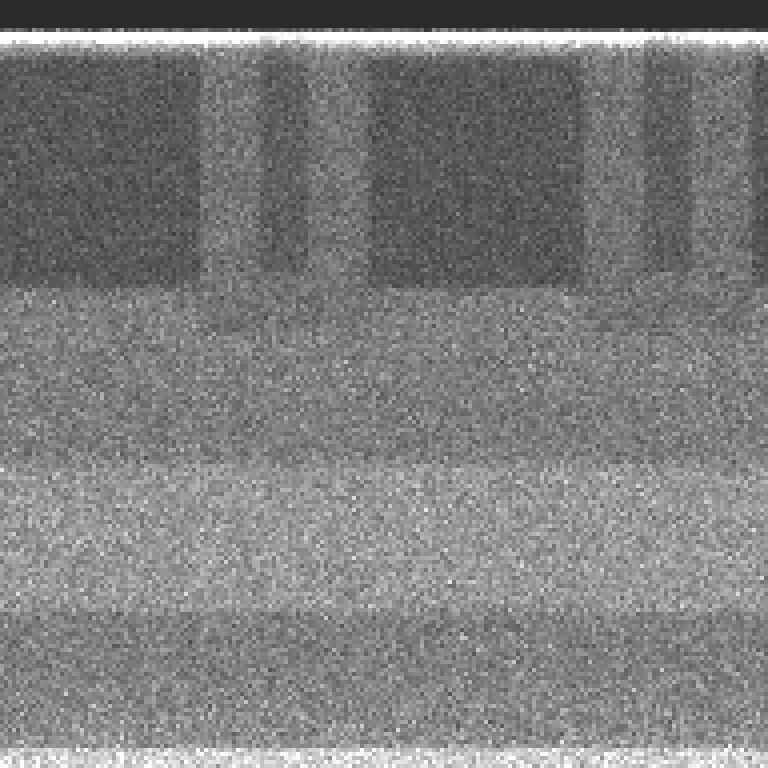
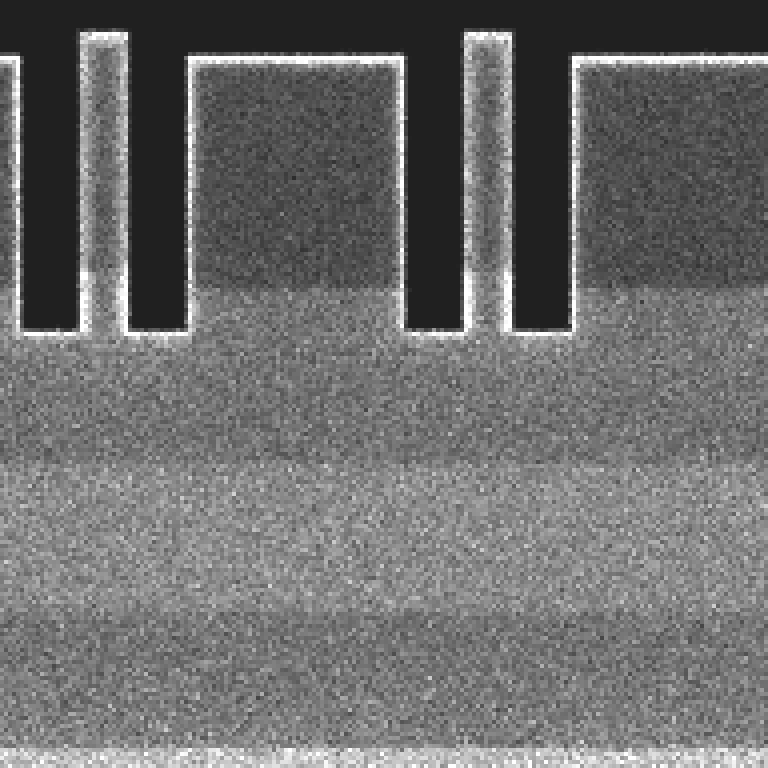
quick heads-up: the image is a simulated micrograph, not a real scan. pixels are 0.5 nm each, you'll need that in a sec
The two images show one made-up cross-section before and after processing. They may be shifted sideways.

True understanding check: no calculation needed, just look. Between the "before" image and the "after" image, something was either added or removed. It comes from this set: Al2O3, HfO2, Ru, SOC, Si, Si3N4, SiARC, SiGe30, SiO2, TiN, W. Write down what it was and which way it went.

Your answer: Al2O3 (removed)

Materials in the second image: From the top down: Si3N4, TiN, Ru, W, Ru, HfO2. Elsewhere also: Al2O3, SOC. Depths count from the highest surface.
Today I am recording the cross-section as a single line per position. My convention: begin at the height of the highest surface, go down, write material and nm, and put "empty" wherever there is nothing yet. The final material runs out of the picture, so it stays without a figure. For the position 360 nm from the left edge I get empty 12, Si3N4 68, TiN 48, Ru 88, W 74, Ru 68, HfO2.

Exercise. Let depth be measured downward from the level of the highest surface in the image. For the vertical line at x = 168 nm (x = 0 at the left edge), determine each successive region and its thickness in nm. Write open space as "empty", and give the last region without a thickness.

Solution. empty 12, Si3N4 68, TiN 48, Ru 88, W 74, Ru 68, HfO2